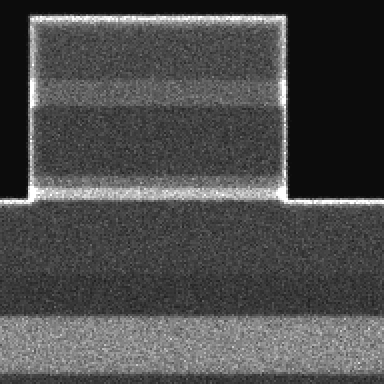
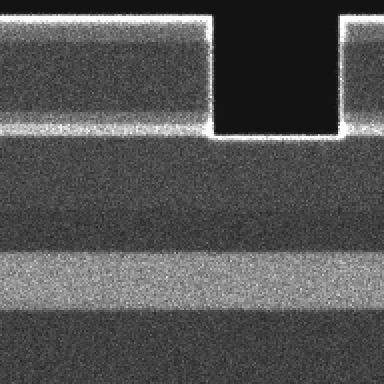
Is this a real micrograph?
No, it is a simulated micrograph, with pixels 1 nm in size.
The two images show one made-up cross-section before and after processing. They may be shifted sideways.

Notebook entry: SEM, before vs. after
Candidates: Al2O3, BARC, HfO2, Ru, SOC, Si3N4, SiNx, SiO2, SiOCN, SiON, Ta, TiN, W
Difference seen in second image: SOC removed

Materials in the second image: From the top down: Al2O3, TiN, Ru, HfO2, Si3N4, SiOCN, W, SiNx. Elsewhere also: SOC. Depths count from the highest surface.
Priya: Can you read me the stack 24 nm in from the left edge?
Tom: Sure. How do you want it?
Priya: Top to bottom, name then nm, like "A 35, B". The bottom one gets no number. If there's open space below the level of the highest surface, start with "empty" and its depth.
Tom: Al2O3 26, TiN 70, Ru 12, HfO2 12, Si3N4 74, SiOCN 42, W 58, SiNx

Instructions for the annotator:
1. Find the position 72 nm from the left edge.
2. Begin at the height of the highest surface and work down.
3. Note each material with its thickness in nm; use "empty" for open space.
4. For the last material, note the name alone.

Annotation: Al2O3 26, TiN 70, Ru 12, HfO2 12, Si3N4 74, SiOCN 42, W 58, SiNx